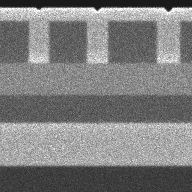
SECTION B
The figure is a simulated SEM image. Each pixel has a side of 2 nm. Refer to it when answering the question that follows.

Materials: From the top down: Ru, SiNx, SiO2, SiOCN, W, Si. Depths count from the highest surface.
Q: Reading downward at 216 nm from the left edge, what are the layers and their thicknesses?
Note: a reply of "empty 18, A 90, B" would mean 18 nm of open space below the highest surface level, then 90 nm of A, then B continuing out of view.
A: Ru 26, SiNx 84, SiO2 64, SiOCN 56, W 86, Si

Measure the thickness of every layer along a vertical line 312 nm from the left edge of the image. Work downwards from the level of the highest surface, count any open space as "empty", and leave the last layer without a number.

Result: Ru 26, SiNx 84, SiO2 64, SiOCN 56, W 86, Si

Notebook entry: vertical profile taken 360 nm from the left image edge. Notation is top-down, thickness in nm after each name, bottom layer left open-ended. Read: Ru 26, SiNx 84, SiO2 64, SiOCN 56, W 86, Si